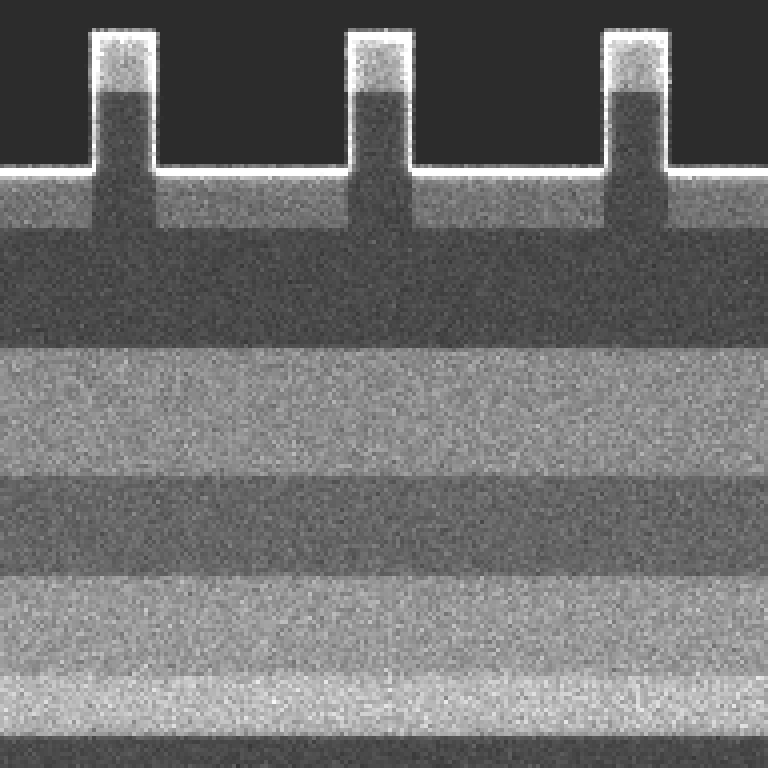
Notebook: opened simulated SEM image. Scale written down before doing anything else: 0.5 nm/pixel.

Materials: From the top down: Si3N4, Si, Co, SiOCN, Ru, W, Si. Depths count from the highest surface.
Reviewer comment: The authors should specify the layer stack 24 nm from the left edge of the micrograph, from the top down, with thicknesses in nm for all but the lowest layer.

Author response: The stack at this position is empty 68, Si3N4 30, Si 60, Co 64, SiOCN 50, Ru 50, W 30, Si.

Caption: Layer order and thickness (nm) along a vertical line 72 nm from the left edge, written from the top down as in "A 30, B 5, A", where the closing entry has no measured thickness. Ru 30, Si 128, Co 64, SiOCN 50, Ru 50, W 30, Si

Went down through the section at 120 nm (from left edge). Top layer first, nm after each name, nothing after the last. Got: empty 68, Si3N4 30, Si 60, Co 64, SiOCN 50, Ru 50, W 30, Si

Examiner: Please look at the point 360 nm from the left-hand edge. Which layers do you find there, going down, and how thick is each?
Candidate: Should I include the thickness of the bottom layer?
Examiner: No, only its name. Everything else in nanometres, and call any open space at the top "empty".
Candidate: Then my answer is empty 68, Si3N4 30, Si 60, Co 64, SiOCN 50, Ru 50, W 30, Si